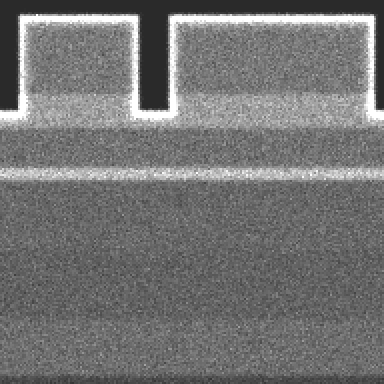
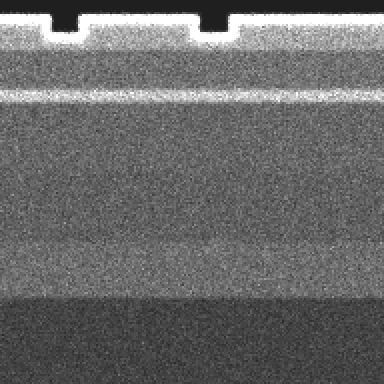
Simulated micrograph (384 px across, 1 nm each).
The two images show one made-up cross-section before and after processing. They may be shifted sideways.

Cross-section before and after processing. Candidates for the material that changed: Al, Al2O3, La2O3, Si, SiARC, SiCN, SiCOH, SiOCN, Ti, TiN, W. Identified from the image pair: SiARC (removed).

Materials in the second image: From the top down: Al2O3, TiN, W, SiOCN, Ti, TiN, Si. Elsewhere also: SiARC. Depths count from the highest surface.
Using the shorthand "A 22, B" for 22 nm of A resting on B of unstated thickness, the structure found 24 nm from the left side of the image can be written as Al2O3 34, TiN 40, W 12, SiOCN 70, Ti 70, TiN 56, Si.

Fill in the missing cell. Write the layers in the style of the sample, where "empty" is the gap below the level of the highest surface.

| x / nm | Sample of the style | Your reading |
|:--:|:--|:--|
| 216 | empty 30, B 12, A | empty 18, Al2O3 16, TiN 40, W 12, SiOCN 70, Ti 70, TiN 56, Si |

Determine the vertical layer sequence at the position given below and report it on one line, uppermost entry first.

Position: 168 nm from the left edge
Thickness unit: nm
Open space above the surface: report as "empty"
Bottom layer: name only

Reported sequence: Al2O3 34, TiN 40, W 12, SiOCN 70, Ti 70, TiN 56, Si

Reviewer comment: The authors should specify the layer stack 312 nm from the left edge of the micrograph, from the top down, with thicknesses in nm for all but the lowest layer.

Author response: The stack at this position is Al2O3 34, TiN 40, W 12, SiOCN 70, Ti 70, TiN 56, Si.